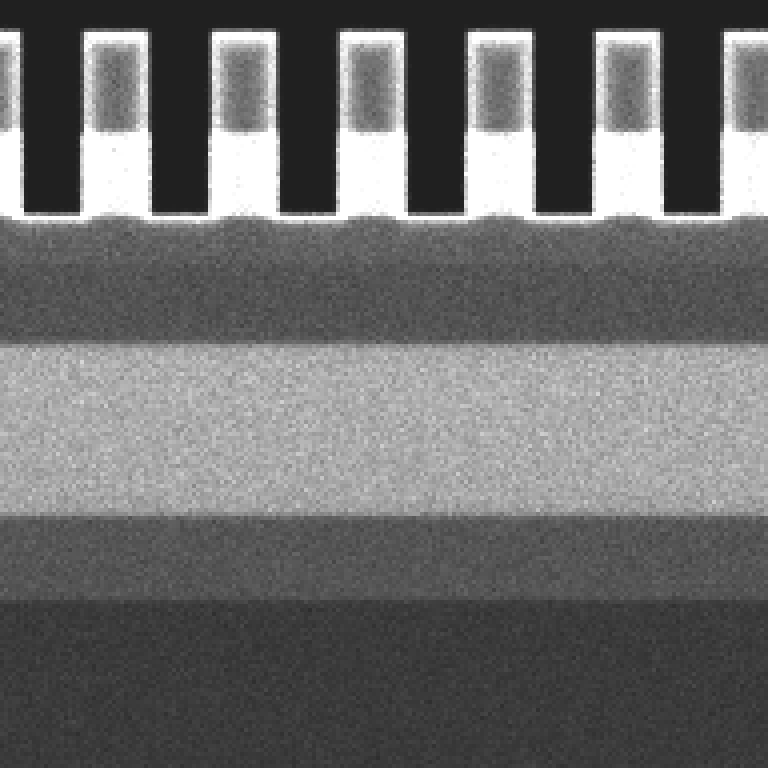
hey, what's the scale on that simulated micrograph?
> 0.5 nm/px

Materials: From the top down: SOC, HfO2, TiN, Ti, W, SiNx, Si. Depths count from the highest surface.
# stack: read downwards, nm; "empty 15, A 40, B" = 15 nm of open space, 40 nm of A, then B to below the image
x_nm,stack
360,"empty 92, TiN 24, Ti 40, W 86, SiNx 42, Si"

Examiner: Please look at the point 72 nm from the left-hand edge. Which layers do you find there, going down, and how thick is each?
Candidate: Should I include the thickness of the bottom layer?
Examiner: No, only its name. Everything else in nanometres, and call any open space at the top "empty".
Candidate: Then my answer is SOC 50, HfO2 42, TiN 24, Ti 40, W 86, SiNx 42, Si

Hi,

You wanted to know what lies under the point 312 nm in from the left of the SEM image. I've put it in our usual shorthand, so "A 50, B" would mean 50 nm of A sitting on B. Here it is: SOC 50, HfO2 42, TiN 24, Ti 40, W 86, SiNx 42, Si